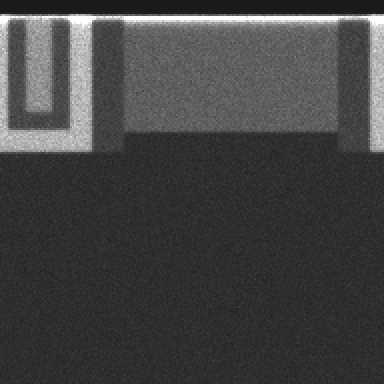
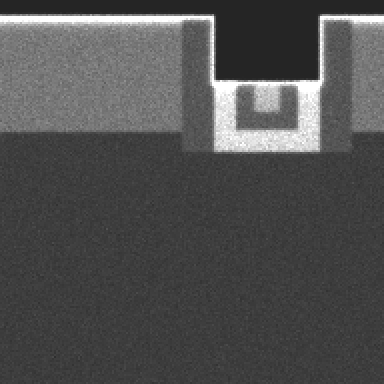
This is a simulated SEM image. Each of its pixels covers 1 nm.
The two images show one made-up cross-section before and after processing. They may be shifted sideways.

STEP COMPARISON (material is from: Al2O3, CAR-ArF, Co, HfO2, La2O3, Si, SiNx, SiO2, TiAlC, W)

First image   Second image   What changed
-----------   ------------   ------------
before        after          HfO2 and TiAlC and W, removed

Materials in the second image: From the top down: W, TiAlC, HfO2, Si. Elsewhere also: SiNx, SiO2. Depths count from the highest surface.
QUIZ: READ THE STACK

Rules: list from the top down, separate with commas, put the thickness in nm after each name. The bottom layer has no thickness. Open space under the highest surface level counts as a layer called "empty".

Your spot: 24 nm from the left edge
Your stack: SiO2 116, Si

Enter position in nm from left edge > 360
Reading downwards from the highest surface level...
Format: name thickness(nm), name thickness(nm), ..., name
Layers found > SiO2 116, Si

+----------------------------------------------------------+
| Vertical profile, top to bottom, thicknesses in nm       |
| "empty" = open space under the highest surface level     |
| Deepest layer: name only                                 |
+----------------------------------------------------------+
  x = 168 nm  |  SiO2 116, Si